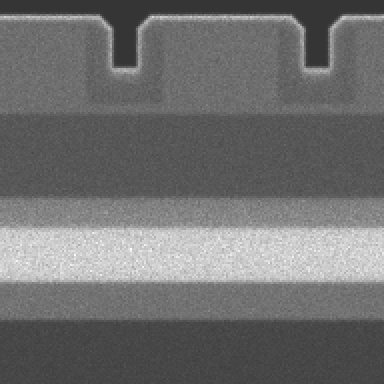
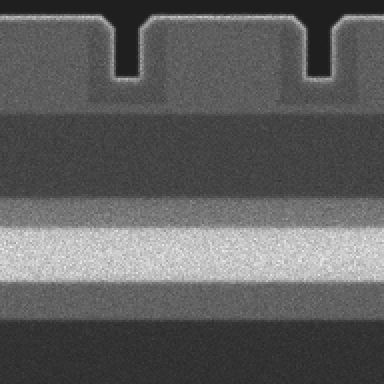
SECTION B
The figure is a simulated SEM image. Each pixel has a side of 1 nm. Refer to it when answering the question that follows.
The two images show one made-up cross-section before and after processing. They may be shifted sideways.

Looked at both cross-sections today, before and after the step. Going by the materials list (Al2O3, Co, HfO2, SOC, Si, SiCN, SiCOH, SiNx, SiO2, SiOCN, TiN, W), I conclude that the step removed SOC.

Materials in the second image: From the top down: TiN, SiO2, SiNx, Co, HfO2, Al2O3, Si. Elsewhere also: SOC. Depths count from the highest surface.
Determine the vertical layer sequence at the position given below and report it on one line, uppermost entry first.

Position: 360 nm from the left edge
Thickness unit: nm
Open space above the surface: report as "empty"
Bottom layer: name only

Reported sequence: TiN 10, SiO2 88, SiNx 84, Co 30, HfO2 54, Al2O3 38, Si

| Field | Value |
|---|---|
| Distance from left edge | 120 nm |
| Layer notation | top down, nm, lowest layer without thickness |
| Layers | empty 62, TiN 26, SiO2 10, SiNx 84, Co 30, HfO2 54, Al2O3 38, Si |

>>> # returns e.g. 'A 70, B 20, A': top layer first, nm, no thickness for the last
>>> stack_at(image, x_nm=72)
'TiN 10, SiO2 88, SiNx 84, Co 30, HfO2 54, Al2O3 38, Si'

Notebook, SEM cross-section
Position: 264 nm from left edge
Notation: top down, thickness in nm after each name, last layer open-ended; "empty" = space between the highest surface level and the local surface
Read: TiN 10, SiO2 88, SiNx 84, Co 30, HfO2 54, Al2O3 38, Si